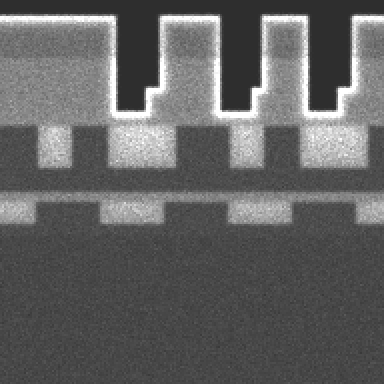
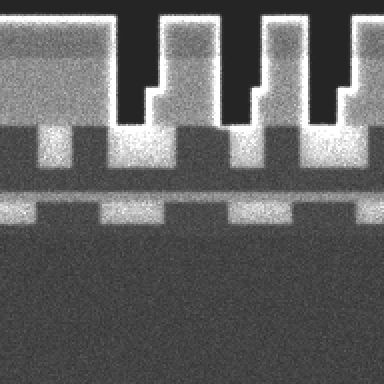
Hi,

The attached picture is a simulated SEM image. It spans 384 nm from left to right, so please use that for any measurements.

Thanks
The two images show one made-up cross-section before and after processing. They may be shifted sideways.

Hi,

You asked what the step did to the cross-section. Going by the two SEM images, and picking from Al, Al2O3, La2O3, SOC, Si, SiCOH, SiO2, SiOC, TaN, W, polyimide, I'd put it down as Al2O3, removed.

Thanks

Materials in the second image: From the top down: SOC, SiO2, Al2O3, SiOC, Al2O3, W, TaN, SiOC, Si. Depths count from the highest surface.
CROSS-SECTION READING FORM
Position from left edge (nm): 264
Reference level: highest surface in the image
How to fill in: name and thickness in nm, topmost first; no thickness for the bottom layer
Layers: SOC 42, SiO2 54, Al2O3 14, SiOC 66, Al2O3 10, W 12, TaN 10, SiOC 12, Si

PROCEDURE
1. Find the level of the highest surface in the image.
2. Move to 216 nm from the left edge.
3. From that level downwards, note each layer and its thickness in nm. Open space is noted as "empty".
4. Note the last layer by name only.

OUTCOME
SOC 42, SiO2 54, Al2O3 14, SiOC 66, Al2O3 10, SiOC 34, Si